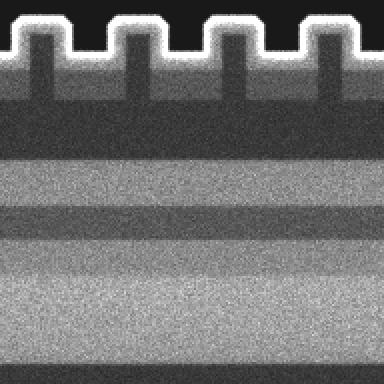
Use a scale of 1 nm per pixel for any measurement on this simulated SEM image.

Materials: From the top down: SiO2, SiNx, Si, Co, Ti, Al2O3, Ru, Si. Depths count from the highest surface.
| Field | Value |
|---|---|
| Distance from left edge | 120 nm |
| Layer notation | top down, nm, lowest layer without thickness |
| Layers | SiO2 54, SiNx 30, Si 60, Co 46, Ti 34, Al2O3 36, Ru 88, Si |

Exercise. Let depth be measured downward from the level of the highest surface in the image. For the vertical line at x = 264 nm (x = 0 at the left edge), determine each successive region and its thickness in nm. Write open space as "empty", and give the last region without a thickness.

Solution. empty 36, SiO2 18, SiNx 30, Si 60, Co 46, Ti 34, Al2O3 36, Ru 88, Si